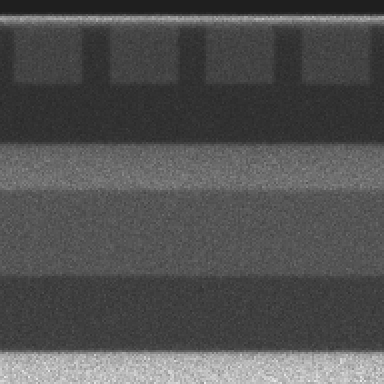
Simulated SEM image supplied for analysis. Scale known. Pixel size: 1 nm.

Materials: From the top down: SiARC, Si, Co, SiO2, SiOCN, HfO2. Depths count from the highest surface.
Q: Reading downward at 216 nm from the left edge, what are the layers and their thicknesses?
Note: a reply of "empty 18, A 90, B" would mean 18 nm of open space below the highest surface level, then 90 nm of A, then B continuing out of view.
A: SiARC 68, Si 60, Co 46, SiO2 86, SiOCN 76, HfO2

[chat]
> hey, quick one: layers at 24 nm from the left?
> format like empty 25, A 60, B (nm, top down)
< SiARC 68, Si 60, Co 46, SiO2 86, SiOCN 76, HfO2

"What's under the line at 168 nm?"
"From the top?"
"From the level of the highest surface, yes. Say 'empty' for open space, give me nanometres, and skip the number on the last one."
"SiARC 68, Si 60, Co 46, SiO2 86, SiOCN 76, HfO2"